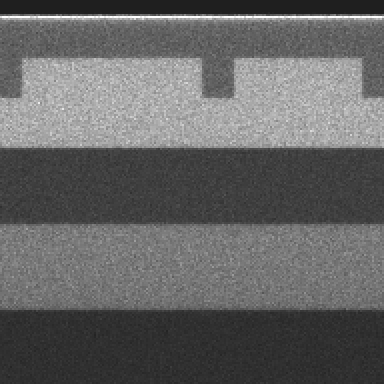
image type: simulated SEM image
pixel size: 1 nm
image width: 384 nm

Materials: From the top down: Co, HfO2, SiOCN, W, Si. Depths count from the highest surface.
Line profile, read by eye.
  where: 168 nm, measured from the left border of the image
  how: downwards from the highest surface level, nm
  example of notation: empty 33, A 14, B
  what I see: Co 42, HfO2 90, SiOCN 76, W 86, Si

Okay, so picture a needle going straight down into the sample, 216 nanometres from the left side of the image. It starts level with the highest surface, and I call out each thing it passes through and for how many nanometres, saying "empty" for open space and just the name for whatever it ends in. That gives Co 82, HfO2 50, SiOCN 76, W 86, Si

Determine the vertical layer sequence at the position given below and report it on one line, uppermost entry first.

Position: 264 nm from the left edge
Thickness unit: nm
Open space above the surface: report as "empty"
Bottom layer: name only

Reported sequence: Co 42, HfO2 90, SiOCN 76, W 86, Si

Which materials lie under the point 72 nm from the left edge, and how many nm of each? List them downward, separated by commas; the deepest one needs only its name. Co 42, HfO2 90, SiOCN 76, W 86, Si